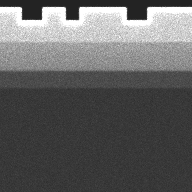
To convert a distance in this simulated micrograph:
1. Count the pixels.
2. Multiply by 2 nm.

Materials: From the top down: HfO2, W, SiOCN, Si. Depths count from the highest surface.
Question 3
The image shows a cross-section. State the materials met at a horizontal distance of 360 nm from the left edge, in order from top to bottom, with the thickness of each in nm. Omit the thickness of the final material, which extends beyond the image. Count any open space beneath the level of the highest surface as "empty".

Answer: HfO2 68, W 58, SiOCN 34, Si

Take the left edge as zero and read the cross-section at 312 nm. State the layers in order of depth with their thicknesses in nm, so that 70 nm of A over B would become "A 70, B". HfO2 68, W 58, SiOCN 34, Si